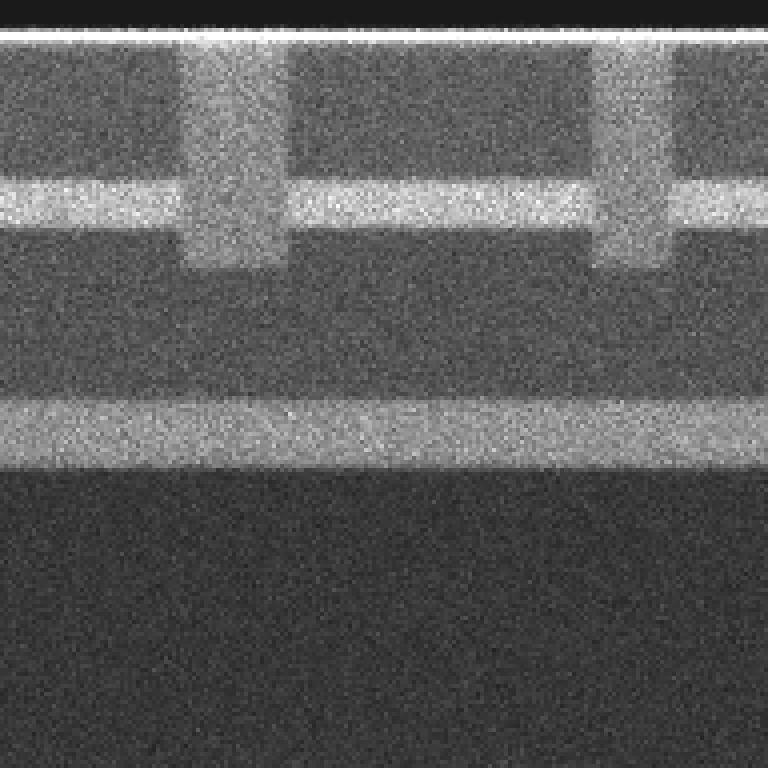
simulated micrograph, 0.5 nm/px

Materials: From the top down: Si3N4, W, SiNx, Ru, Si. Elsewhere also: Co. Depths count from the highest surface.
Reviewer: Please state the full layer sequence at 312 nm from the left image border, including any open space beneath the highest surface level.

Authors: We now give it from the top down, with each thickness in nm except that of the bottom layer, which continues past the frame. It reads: Co 118, SiNx 66, Ru 34, Si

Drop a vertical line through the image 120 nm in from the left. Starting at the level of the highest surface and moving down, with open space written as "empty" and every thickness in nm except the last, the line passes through Co 118, SiNx 66, Ru 34, Si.